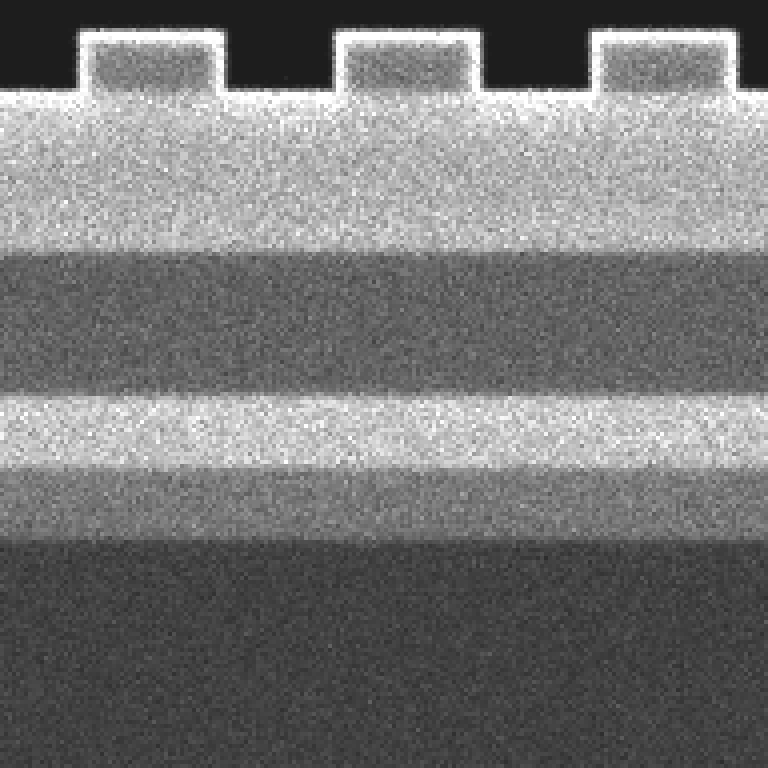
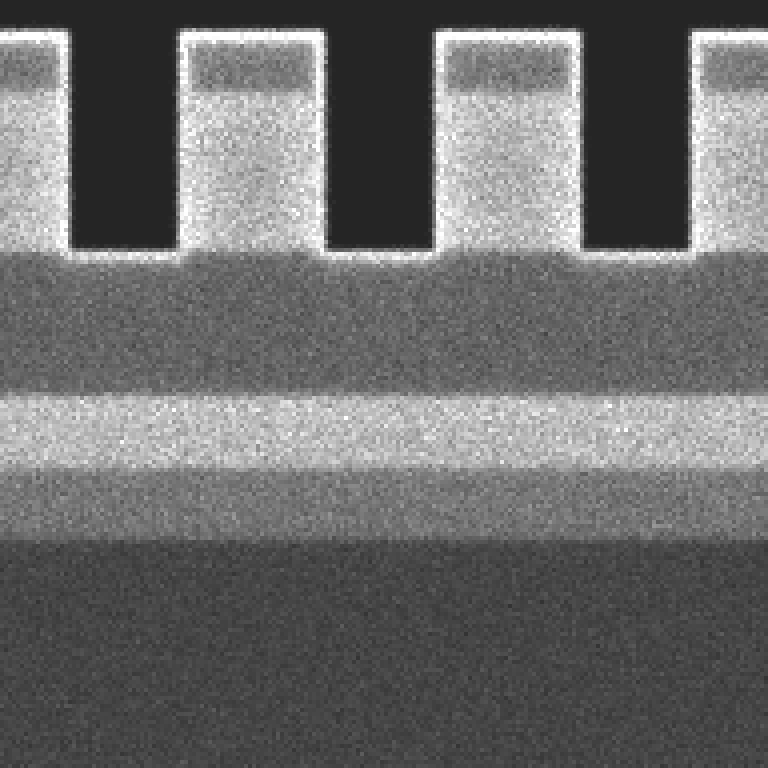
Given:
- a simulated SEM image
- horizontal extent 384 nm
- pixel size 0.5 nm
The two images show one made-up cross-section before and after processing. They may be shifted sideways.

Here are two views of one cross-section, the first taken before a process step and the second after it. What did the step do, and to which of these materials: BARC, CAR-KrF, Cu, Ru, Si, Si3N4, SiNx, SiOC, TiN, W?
It removed Ru.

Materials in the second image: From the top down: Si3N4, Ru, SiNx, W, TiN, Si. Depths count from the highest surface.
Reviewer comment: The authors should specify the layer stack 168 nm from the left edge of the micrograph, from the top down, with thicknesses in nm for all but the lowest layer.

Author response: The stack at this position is empty 110, SiNx 72, W 36, TiN 36, Si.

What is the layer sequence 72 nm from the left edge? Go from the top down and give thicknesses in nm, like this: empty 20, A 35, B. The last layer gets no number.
empty 110, SiNx 72, W 36, TiN 36, Si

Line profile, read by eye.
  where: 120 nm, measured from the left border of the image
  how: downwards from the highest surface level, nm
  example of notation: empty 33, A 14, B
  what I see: Si3N4 30, Ru 80, SiNx 72, W 36, TiN 36, Si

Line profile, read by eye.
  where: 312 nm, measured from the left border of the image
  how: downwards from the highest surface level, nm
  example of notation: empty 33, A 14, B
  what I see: empty 110, SiNx 72, W 36, TiN 36, Si